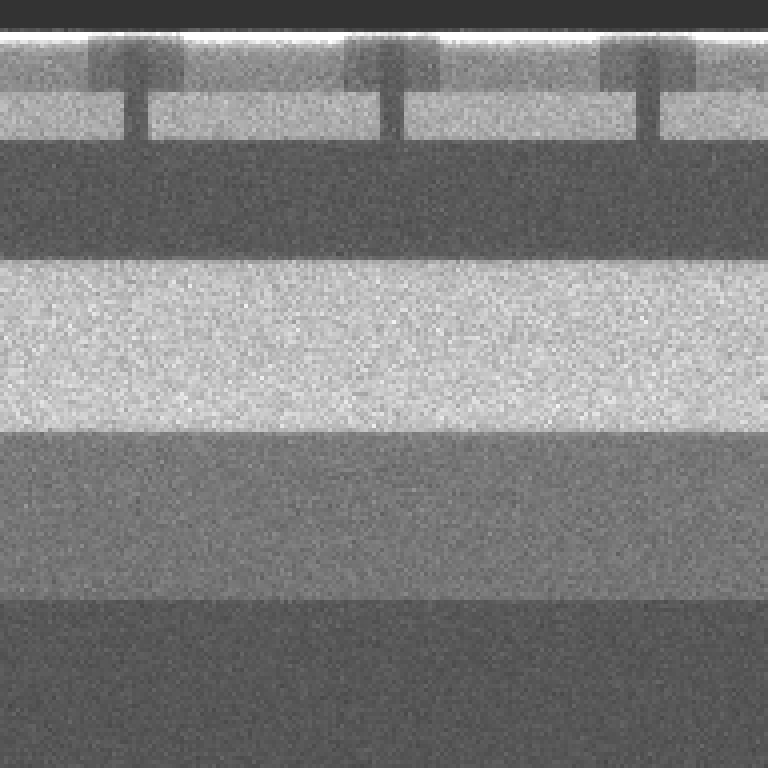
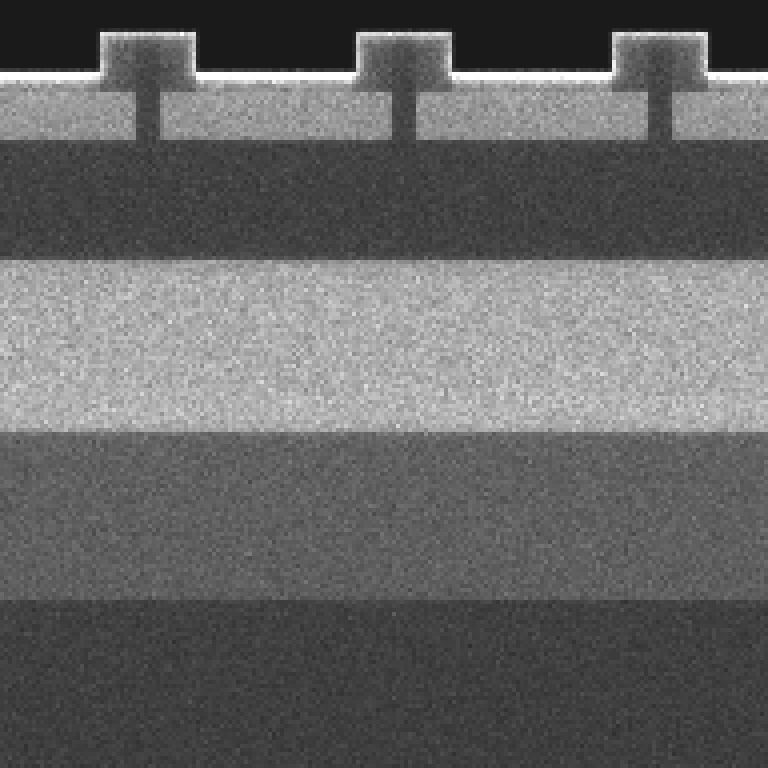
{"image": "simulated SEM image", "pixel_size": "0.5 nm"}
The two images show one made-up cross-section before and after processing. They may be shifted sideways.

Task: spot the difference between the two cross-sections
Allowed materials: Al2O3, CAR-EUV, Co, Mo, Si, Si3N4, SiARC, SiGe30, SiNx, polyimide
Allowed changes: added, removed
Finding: removed Si3N4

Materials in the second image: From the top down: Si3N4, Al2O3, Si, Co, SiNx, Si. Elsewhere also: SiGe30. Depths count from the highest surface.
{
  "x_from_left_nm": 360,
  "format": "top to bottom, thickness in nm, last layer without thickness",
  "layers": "empty 20, Si3N4 10, Al2O3 24, Si 60, Co 86, SiNx 84, Si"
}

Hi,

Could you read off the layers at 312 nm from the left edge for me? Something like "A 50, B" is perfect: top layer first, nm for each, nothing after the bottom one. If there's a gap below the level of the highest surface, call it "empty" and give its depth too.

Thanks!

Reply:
SiGe30 30, Al2O3 24, Si 60, Co 86, SiNx 84, Si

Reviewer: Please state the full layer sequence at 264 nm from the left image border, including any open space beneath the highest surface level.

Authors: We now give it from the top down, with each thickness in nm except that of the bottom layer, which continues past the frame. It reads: empty 20, Si3N4 10, Al2O3 24, Si 60, Co 86, SiNx 84, Si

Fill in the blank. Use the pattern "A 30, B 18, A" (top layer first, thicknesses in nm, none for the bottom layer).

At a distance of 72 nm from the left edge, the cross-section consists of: Si 114, Co 86, SiNx 84, Si